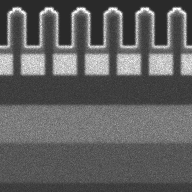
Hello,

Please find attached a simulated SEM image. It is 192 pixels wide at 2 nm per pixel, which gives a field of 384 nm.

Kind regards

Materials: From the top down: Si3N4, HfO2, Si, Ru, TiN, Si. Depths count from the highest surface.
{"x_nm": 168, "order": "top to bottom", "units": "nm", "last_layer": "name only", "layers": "Si3N4 16, Si 178, Ru 76, TiN 80, Si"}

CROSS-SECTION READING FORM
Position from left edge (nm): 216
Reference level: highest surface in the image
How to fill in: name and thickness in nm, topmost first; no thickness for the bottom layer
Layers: empty 6, Si3N4 86, HfO2 42, Si 60, Ru 76, TiN 80, Si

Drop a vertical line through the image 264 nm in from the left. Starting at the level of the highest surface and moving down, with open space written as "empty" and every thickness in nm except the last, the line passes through empty 76, Si3N4 16, HfO2 42, Si 60, Ru 76, TiN 80, Si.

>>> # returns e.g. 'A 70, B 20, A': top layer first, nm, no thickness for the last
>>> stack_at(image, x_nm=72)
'empty 76, Si3N4 16, HfO2 42, Si 60, Ru 76, TiN 80, Si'